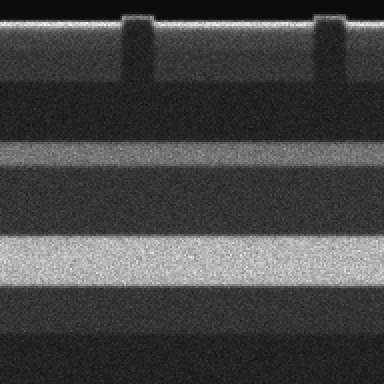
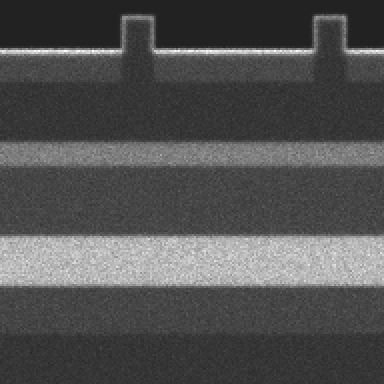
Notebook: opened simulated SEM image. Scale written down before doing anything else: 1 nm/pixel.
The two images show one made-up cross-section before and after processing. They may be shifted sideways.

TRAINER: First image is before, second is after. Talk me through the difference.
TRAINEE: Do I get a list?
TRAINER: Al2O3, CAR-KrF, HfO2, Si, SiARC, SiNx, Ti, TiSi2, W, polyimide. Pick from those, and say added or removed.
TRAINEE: removed: SiARC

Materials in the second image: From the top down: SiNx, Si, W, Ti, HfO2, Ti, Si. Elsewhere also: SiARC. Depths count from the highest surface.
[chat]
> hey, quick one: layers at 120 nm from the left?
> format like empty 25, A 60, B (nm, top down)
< empty 34, SiNx 32, Si 60, W 24, Ti 70, HfO2 50, Ti 48, Si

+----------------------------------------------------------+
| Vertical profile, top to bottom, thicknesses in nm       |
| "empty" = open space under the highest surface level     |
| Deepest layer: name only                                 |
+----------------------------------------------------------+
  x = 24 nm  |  empty 34, SiNx 32, Si 60, W 24, Ti 70, HfO2 50, Ti 48, Si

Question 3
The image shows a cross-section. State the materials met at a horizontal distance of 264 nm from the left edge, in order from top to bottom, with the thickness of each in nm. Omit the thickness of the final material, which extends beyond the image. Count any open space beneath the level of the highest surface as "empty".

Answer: empty 34, SiNx 32, Si 60, W 24, Ti 70, HfO2 50, Ti 48, Si